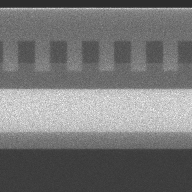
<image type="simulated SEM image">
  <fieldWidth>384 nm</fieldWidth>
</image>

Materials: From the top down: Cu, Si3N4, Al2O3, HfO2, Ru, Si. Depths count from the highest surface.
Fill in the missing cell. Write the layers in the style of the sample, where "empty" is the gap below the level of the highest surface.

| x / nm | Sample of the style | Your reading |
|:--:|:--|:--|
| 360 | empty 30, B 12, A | Cu 66, Si3N4 44, Al2O3 52, HfO2 86, Ru 34, Si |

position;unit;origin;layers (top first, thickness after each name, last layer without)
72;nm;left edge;Cu 126, Al2O3 36, HfO2 86, Ru 34, Si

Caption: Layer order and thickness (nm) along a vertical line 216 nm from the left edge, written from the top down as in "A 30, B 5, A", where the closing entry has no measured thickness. Cu 126, Al2O3 36, HfO2 86, Ru 34, Si